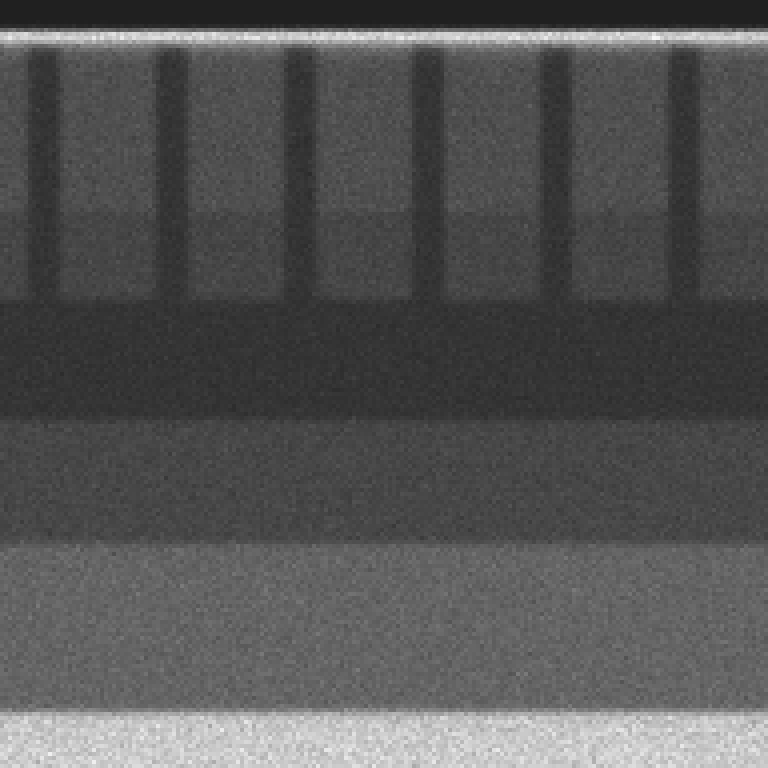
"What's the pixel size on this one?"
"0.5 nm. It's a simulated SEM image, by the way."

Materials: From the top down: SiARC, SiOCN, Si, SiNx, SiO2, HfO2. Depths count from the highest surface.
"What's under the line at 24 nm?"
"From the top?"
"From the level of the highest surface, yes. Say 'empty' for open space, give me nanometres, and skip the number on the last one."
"SiARC 6, Si 188, SiNx 62, SiO2 84, HfO2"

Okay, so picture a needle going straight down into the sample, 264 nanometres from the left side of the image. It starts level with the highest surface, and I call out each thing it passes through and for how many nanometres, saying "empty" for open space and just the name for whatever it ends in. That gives SiARC 90, SiOCN 44, Si 60, SiNx 62, SiO2 84, HfO2